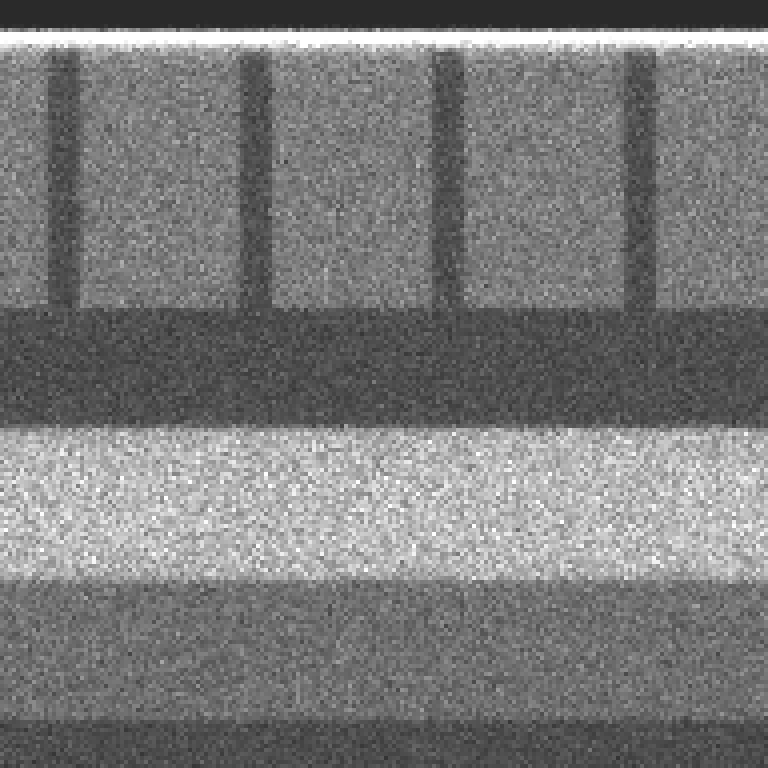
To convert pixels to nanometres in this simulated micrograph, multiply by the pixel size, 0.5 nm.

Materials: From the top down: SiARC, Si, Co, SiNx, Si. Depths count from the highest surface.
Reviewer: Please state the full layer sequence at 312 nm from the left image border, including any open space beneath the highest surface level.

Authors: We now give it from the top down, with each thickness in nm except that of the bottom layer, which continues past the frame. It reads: SiARC 8, Si 190, Co 76, SiNx 70, Si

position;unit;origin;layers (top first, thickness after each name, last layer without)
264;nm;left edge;SiARC 138, Si 60, Co 76, SiNx 70, Si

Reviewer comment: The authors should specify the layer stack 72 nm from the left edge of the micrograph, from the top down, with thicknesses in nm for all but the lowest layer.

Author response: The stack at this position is SiARC 138, Si 60, Co 76, SiNx 70, Si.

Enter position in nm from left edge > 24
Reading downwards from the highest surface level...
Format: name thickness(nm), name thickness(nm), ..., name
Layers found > SiARC 8, Si 190, Co 76, SiNx 70, Si